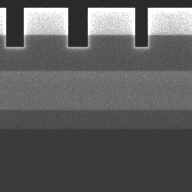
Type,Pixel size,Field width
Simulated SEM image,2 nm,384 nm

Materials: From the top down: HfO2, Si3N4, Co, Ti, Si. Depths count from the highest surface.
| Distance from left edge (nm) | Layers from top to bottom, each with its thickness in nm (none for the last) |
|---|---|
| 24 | empty 78, Si3N4 48, Co 78, Ti 38, Si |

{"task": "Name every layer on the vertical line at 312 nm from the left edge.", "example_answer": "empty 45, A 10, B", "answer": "HfO2 54, Si3N4 72, Co 78, Ti 38, Si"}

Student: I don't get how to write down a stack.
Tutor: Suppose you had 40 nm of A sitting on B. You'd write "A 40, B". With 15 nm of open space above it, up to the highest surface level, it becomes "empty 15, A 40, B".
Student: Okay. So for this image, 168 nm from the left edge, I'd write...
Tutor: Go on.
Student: empty 78, Si3N4 48, Co 78, Ti 38, Si